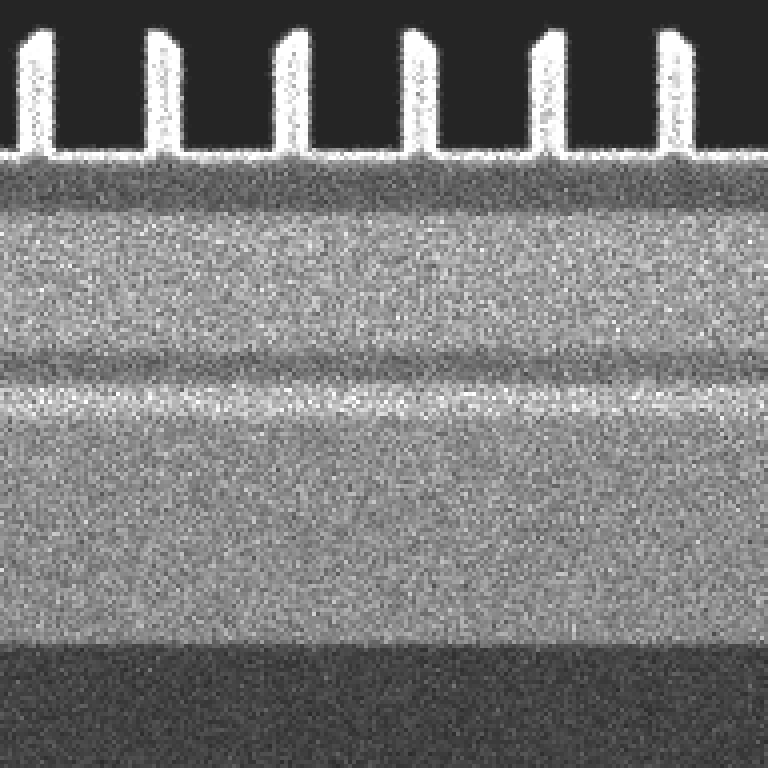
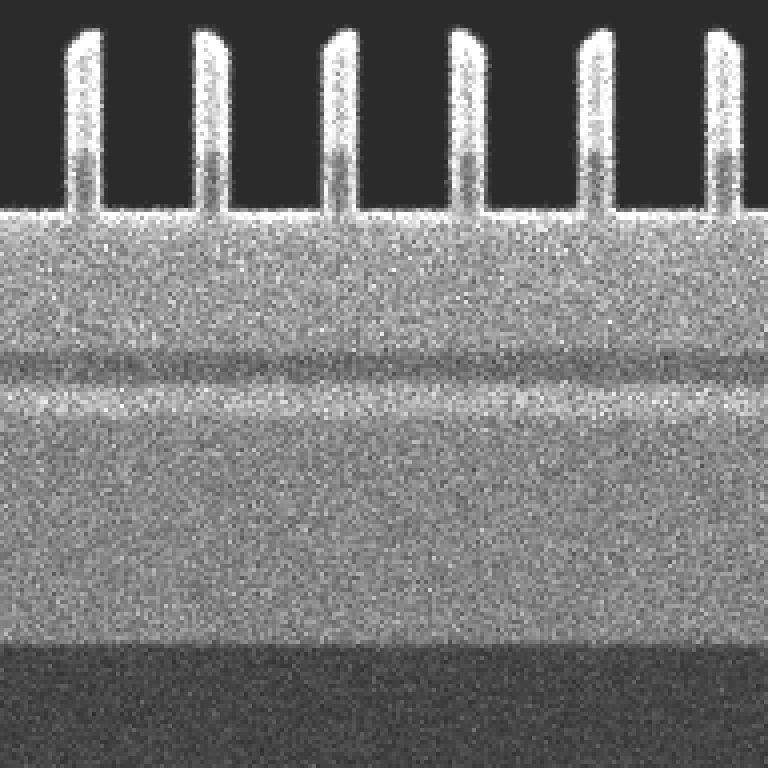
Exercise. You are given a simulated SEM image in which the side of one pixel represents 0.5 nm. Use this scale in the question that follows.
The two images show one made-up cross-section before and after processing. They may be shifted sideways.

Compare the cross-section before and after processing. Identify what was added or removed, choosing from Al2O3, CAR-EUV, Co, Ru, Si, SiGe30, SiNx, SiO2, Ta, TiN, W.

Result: SiNx removed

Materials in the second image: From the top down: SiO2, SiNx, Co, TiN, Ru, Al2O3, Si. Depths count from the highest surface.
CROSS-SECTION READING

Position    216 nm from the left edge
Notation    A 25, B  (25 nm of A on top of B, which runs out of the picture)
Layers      empty 90, Co 70, TiN 16, Ru 16, Al2O3 114, Si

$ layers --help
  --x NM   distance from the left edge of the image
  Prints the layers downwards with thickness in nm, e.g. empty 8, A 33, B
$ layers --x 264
empty 90, Co 70, TiN 16, Ru 16, Al2O3 114, Si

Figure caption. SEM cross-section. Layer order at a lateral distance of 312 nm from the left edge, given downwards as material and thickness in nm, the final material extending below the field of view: empty 90, Co 70, TiN 16, Ru 16, Al2O3 114, Si